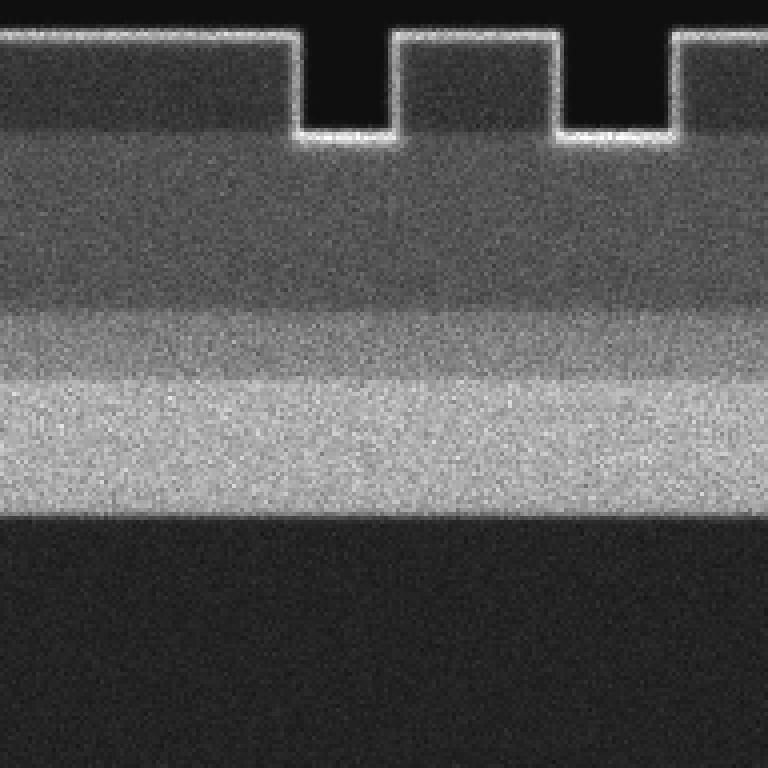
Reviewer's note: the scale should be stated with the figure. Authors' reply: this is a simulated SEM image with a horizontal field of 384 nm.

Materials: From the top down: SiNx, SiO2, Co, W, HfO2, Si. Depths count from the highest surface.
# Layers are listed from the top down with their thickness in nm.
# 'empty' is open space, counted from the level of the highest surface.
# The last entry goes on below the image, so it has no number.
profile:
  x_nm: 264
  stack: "SiNx 50, SiO2 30, Co 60, W 34, HfO2 68, Si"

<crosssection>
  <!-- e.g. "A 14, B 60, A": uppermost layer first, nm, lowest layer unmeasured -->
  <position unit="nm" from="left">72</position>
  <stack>SiNx 50, SiO2 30, Co 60, W 34, HfO2 68, Si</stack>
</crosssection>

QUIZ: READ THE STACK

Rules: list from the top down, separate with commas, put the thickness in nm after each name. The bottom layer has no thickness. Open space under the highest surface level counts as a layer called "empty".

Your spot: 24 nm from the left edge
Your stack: SiNx 50, SiO2 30, Co 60, W 34, HfO2 68, Si